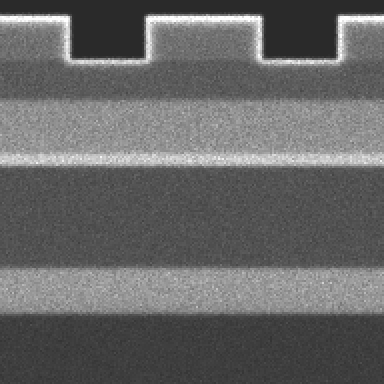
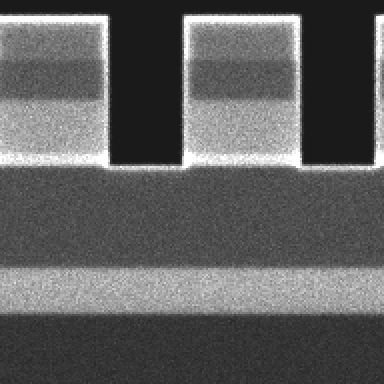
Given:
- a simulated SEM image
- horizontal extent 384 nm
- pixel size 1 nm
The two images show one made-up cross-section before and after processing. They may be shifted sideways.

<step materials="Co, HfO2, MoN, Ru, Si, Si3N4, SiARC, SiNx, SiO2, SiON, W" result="removed HfO2 and Ru and Si3N4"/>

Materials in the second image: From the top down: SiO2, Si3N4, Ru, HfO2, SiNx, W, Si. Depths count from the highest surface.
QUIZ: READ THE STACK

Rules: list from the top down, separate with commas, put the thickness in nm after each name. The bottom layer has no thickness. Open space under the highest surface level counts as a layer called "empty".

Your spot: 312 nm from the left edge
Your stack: empty 150, SiNx 102, W 46, Si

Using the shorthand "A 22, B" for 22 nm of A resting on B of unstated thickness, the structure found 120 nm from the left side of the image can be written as empty 150, SiNx 102, W 46, Si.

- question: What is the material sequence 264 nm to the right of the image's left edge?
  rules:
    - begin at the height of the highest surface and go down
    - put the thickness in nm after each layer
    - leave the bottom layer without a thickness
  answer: SiO2 44, Si3N4 40, Ru 54, HfO2 12, SiNx 102, W 46, Si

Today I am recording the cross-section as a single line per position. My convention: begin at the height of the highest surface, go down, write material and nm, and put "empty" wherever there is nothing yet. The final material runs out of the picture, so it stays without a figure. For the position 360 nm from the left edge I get empty 150, SiNx 102, W 46, Si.